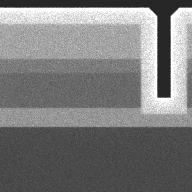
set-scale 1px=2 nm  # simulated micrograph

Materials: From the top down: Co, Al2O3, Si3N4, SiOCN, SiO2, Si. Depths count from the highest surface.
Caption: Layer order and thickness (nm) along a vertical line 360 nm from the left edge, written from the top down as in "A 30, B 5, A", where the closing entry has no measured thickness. Co 212, SiO2 26, Si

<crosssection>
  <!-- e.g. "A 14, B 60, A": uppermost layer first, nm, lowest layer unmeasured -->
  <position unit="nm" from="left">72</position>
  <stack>Co 32, Al2O3 70, Si3N4 28, SiOCN 70, SiO2 38, Si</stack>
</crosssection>